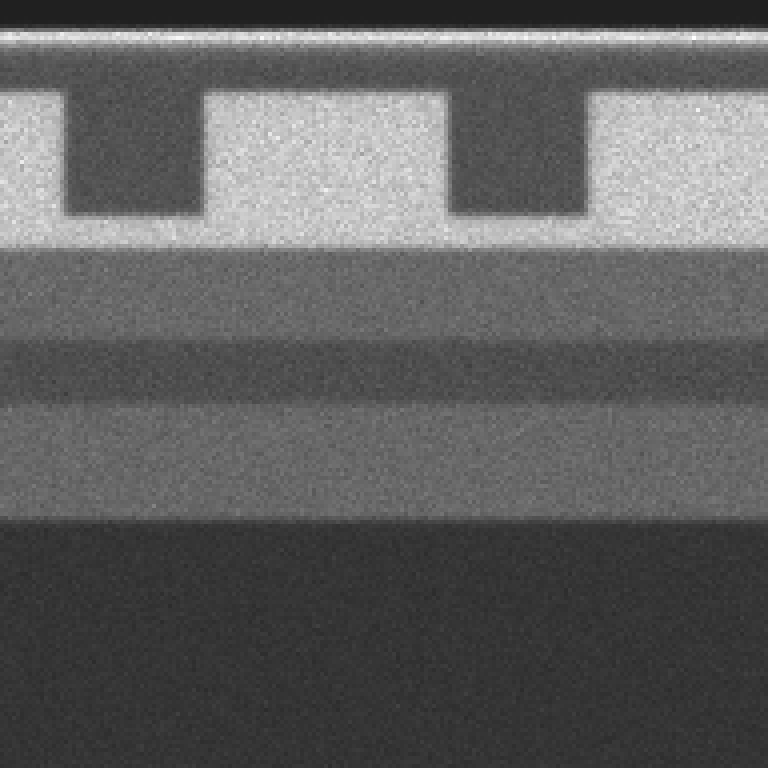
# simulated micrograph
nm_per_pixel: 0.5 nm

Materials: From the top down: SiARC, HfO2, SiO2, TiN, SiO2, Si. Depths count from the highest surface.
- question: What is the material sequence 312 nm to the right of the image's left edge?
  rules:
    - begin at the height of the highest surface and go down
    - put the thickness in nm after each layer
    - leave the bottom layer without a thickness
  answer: SiARC 30, HfO2 78, SiO2 46, TiN 32, SiO2 58, Si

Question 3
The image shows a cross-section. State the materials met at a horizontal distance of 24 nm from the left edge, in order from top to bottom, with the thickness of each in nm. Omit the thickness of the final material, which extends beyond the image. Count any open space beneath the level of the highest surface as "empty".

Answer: SiARC 30, HfO2 78, SiO2 46, TiN 32, SiO2 58, Si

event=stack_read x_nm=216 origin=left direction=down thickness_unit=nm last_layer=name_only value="SiARC 30, HfO2 78, SiO2 46, TiN 32, SiO2 58, Si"